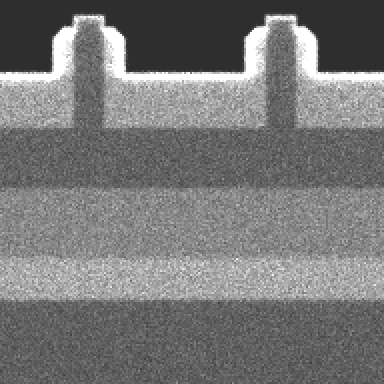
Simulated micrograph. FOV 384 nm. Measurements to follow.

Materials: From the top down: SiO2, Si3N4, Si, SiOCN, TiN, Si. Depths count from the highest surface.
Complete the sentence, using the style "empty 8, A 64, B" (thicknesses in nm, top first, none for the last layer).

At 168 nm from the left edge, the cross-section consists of empty 58, Si3N4 54, Si 60, SiOCN 70, TiN 42, Si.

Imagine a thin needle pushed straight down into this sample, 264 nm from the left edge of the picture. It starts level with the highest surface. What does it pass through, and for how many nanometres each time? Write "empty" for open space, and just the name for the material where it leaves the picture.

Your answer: empty 12, SiO2 46, Si3N4 54, Si 60, SiOCN 70, TiN 42, Si